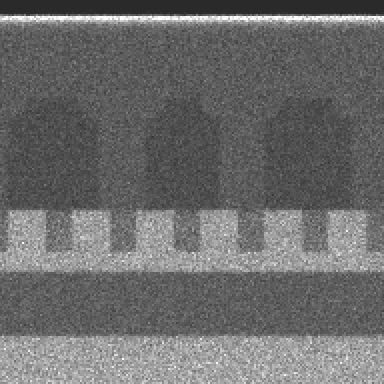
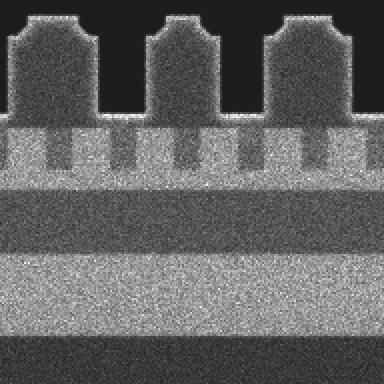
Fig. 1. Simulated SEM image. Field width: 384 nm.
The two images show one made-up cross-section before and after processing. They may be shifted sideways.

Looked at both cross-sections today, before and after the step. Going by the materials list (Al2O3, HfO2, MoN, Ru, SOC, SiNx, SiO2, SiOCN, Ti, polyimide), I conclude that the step removed SiO2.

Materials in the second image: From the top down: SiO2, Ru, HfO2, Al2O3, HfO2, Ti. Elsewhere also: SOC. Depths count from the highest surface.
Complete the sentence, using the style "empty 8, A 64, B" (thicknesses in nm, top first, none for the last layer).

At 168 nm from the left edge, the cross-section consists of SOC 112, HfO2 62, Al2O3 64, HfO2 82, Ti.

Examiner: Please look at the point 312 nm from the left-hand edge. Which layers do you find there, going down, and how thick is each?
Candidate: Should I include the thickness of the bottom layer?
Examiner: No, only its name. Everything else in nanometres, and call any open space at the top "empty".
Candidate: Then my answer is SOC 112, Ru 42, HfO2 20, Al2O3 64, HfO2 82, Ti